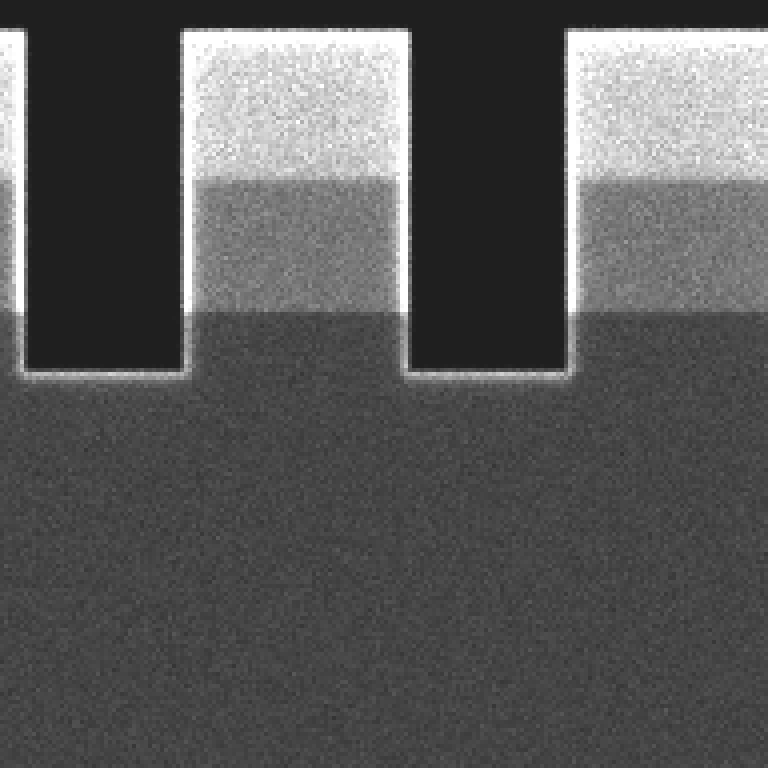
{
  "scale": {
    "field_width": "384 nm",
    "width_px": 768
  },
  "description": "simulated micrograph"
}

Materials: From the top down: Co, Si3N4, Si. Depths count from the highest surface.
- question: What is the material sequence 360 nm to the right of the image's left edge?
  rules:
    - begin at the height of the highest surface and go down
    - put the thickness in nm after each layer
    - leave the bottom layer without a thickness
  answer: Co 74, Si3N4 66, Si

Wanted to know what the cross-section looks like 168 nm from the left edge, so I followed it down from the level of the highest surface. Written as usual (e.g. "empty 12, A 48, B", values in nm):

Co 74, Si3N4 66, Si